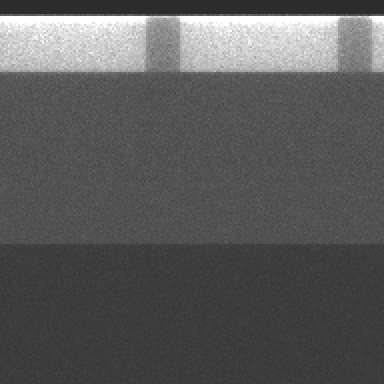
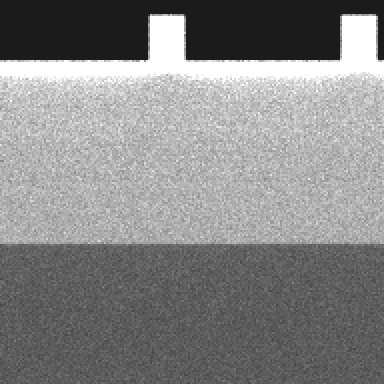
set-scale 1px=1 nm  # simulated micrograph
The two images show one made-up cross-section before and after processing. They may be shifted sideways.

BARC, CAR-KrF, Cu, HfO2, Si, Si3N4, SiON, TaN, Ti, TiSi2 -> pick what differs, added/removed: HfO2 removed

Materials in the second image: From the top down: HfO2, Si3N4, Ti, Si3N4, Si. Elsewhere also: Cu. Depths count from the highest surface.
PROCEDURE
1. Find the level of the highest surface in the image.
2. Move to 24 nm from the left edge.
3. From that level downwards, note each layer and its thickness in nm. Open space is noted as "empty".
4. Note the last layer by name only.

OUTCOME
empty 46, HfO2 10, Si3N4 50, Ti 60, Si3N4 62, Si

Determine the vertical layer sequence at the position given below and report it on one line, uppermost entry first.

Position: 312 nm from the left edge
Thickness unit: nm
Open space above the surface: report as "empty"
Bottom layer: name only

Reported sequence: empty 46, HfO2 10, Si3N4 50, Ti 60, Si3N4 62, Si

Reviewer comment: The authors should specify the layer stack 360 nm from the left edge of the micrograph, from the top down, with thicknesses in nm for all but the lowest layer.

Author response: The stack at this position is Cu 56, Si3N4 50, Ti 60, Si3N4 62, Si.